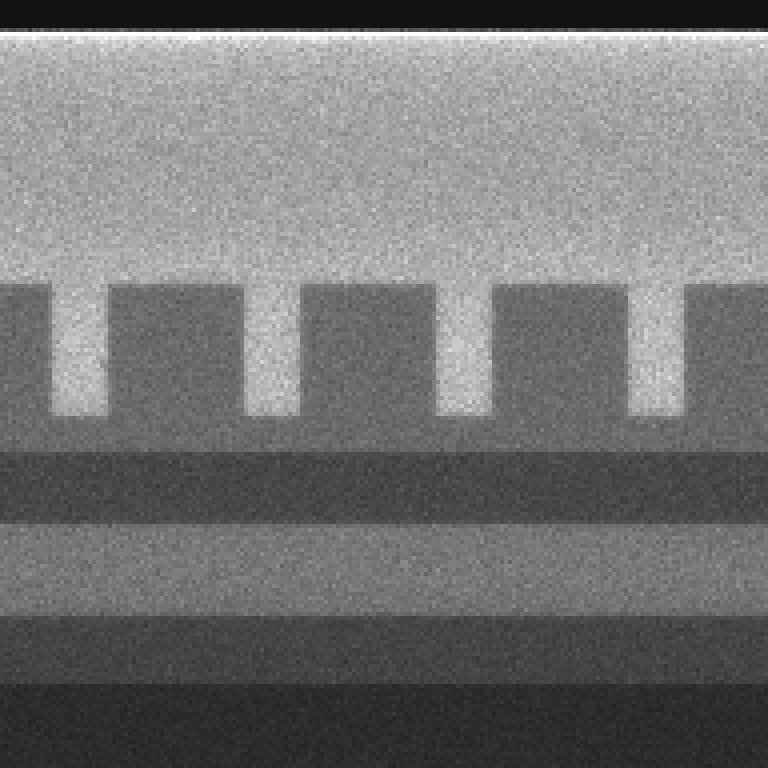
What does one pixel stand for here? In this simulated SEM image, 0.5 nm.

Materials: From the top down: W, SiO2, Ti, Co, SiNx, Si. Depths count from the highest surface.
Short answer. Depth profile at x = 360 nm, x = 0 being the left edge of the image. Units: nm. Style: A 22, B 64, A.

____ W 126, SiO2 84, Ti 36, Co 46, SiNx 34, Si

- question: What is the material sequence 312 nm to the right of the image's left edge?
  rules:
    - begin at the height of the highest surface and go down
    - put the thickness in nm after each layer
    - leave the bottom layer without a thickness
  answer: W 126, SiO2 84, Ti 36, Co 46, SiNx 34, Si